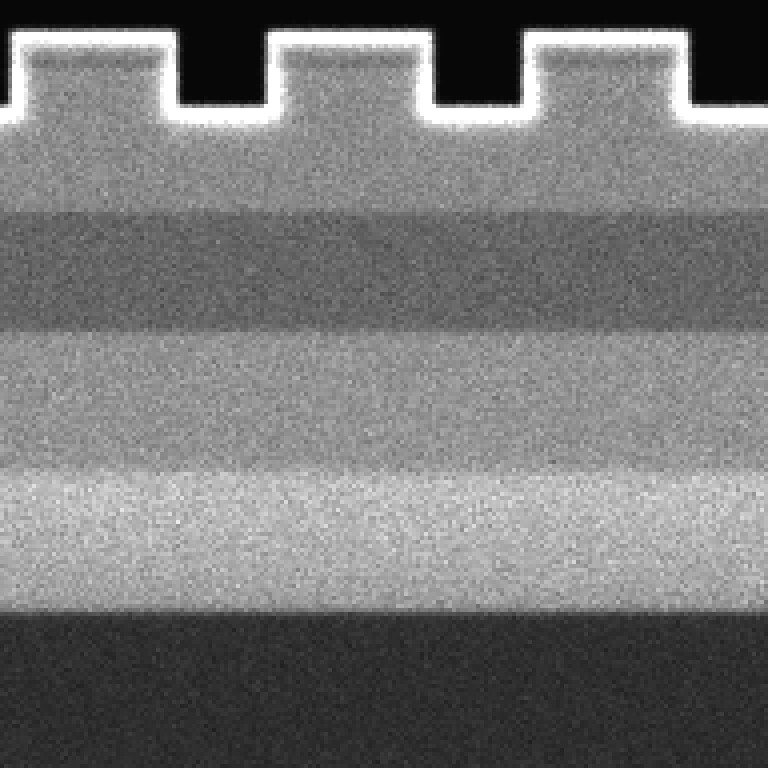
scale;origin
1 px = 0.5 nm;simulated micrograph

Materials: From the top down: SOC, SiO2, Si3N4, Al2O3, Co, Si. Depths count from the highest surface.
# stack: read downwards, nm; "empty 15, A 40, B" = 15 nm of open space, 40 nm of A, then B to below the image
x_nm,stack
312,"SOC 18, SiO2 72, Si3N4 60, Al2O3 70, Co 70, Si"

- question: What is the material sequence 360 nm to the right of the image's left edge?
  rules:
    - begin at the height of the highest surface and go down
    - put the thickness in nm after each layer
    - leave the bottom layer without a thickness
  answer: empty 38, SiO2 52, Si3N4 60, Al2O3 70, Co 70, Si